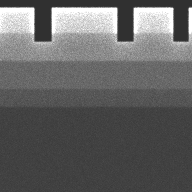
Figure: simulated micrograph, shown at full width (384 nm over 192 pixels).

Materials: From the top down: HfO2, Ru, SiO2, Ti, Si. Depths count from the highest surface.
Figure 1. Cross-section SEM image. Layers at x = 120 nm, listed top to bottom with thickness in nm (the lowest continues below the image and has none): HfO2 50, Ru 56, SiO2 56, Ti 36, Si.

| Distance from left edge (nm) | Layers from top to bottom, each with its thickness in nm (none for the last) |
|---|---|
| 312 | HfO2 50, Ru 56, SiO2 56, Ti 36, Si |